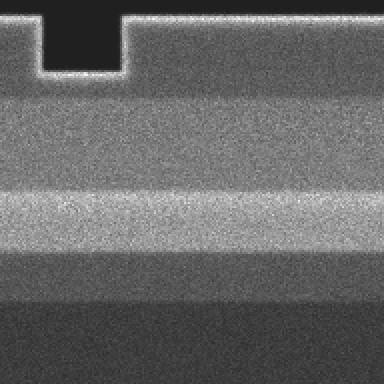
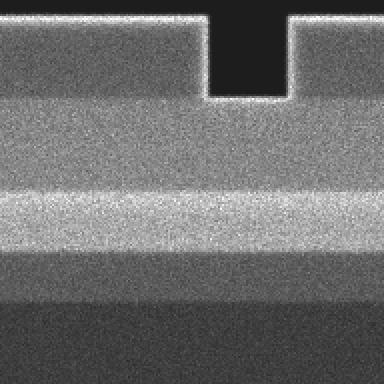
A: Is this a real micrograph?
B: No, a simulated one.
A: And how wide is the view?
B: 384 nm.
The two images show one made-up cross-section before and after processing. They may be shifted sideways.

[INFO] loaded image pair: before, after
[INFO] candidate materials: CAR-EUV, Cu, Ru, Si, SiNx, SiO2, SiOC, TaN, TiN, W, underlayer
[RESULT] removed underlayer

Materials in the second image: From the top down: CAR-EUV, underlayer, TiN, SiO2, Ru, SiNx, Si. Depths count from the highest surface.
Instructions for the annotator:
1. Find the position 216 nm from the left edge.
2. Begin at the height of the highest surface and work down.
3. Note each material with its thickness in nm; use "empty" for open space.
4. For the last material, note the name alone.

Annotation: empty 82, TiN 46, SiO2 48, Ru 60, SiNx 50, Si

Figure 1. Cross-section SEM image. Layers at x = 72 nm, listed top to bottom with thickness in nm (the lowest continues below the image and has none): CAR-EUV 56, underlayer 26, TiN 46, SiO2 48, Ru 60, SiNx 50, Si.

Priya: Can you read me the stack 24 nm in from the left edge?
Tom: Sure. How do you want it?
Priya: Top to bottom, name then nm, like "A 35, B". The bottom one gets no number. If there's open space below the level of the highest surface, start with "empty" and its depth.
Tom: CAR-EUV 56, underlayer 26, TiN 46, SiO2 48, Ru 60, SiNx 50, Si